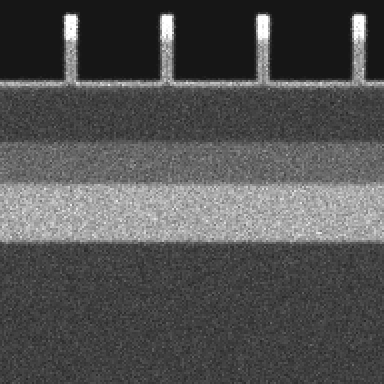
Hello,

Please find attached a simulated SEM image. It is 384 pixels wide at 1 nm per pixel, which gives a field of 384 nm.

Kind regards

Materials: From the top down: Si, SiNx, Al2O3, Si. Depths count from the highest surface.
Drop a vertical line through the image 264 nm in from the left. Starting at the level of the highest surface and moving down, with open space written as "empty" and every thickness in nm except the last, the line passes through Si 126, SiNx 42, Al2O3 58, Si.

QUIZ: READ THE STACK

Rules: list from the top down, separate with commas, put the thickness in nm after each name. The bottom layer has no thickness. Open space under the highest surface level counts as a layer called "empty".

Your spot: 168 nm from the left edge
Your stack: Si 126, SiNx 42, Al2O3 58, Si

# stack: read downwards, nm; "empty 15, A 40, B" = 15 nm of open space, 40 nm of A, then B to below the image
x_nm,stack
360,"Si 126, SiNx 42, Al2O3 58, Si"